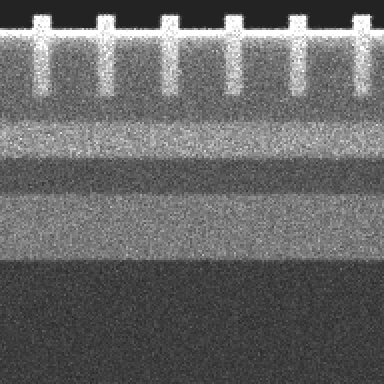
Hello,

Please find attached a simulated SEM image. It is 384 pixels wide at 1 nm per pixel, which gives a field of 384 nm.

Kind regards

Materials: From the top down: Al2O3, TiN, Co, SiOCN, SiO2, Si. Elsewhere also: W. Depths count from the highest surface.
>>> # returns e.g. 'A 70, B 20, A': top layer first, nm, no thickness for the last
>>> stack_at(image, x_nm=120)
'empty 14, Al2O3 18, TiN 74, Co 36, SiOCN 36, SiO2 66, Si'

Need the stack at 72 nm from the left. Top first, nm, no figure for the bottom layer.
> empty 14, Al2O3 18, TiN 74, Co 36, SiOCN 36, SiO2 66, Si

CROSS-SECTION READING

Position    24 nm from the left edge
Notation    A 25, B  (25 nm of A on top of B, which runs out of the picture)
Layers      empty 14, Al2O3 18, TiN 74, Co 36, SiOCN 36, SiO2 66, Si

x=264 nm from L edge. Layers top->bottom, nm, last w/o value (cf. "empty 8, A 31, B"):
empty 14, Al2O3 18, TiN 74, Co 36, SiOCN 36, SiO2 66, Si